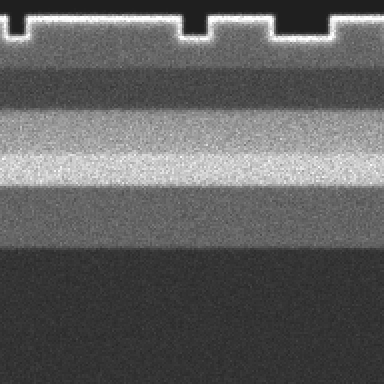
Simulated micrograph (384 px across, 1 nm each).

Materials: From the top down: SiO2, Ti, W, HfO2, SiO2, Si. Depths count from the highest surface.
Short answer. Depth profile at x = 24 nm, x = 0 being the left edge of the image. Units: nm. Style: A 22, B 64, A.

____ empty 20, SiO2 32, Ti 42, W 44, HfO2 32, SiO2 62, Si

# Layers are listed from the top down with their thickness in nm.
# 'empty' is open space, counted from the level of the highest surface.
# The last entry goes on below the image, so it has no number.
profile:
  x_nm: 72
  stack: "SiO2 52, Ti 42, W 44, HfO2 32, SiO2 62, Si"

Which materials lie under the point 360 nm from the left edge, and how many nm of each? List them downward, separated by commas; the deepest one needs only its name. SiO2 52, Ti 42, W 44, HfO2 32, SiO2 62, Si